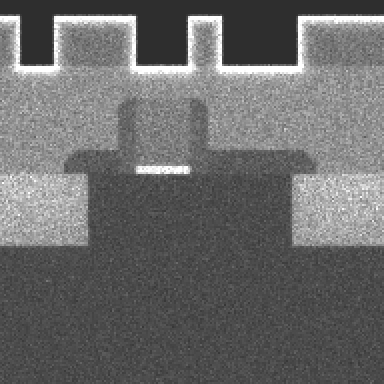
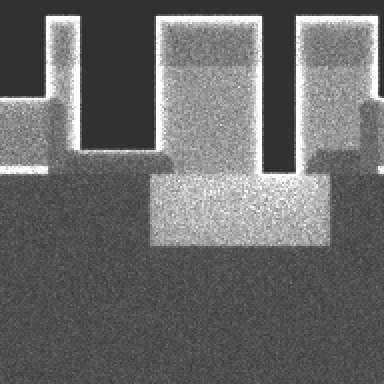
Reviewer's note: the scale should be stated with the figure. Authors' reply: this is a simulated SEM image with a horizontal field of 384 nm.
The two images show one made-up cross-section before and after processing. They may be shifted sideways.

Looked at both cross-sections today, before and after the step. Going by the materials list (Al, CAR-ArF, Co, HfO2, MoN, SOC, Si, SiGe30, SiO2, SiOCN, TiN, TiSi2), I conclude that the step removed SiO2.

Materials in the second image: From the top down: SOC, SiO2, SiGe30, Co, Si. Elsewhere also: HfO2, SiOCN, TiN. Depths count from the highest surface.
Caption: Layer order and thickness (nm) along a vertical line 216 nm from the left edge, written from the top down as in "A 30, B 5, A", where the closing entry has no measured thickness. SOC 50, SiO2 108, Co 72, Si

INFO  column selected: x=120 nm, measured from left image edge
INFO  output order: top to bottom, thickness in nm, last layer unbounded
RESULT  empty 134, SiGe30 24, Si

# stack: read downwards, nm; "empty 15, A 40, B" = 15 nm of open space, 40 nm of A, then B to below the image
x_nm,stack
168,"SOC 50, SiO2 92, SiGe30 16, Co 72, Si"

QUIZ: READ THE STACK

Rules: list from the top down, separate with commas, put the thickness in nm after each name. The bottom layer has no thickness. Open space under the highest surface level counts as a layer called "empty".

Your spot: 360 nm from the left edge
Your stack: SOC 50, SiO2 40, SiOCN 68, Si